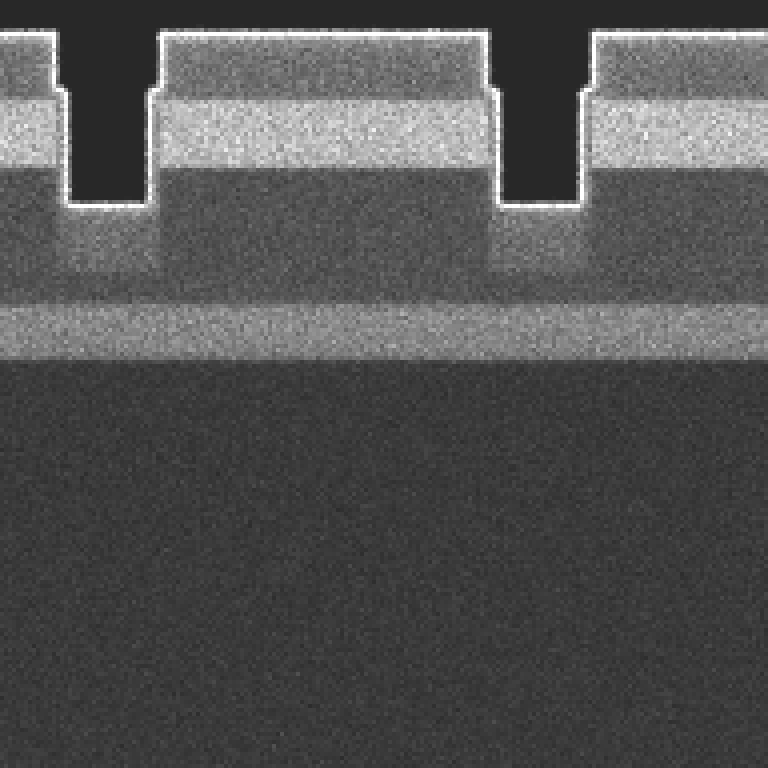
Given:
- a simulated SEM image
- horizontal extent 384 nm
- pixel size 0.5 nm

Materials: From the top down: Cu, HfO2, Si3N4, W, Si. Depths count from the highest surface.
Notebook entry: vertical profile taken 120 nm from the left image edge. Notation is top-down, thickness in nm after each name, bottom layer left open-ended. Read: Cu 34, HfO2 34, Si3N4 68, W 28, Si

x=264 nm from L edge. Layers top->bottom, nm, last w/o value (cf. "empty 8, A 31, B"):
empty 86, Cu 34, Si3N4 16, W 28, Si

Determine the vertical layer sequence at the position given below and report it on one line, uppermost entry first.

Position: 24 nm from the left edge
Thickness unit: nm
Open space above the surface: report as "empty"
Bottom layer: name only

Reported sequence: Cu 34, HfO2 34, Si3N4 68, W 28, Si